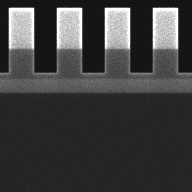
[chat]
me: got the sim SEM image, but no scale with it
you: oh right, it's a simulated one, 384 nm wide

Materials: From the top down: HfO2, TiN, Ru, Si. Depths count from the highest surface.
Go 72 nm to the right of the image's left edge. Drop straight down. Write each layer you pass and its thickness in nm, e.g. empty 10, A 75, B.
empty 130, TiN 12, Ru 28, Si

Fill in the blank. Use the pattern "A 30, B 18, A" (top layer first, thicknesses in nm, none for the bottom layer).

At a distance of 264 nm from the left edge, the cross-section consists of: empty 130, TiN 12, Ru 28, Si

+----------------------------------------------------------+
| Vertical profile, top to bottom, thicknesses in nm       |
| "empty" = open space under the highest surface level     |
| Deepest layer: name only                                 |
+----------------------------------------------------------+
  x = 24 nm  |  HfO2 82, TiN 60, Ru 28, Si